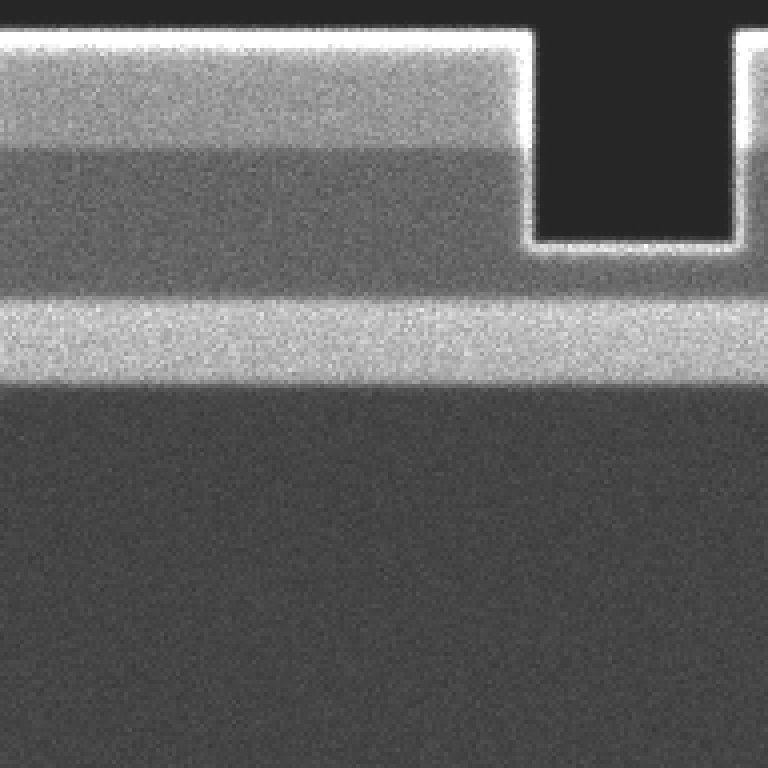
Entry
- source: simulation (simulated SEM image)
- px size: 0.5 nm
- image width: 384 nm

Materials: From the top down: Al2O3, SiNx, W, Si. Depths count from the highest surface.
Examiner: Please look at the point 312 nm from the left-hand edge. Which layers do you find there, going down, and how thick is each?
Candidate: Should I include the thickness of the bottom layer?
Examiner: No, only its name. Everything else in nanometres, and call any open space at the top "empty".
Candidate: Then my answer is empty 106, SiNx 28, W 42, Si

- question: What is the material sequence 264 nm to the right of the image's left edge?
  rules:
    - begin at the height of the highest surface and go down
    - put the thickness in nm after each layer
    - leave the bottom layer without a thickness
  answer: Al2O3 58, SiNx 76, W 42, Si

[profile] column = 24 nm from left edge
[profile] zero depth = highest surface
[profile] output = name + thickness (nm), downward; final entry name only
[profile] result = Al2O3 58, SiNx 76, W 42, Si